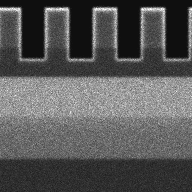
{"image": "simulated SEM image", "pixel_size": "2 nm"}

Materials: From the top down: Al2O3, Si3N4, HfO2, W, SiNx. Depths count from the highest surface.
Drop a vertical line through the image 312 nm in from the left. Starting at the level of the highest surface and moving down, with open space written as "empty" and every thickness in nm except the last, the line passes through Al2O3 80, Si3N4 58, HfO2 80, W 84, SiNx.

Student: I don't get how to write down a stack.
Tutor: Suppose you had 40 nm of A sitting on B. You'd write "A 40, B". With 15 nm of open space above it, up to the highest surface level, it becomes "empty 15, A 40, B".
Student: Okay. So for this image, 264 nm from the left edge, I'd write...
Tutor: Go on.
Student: empty 102, Si3N4 36, HfO2 80, W 84, SiNx